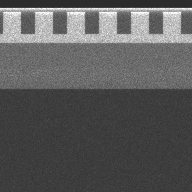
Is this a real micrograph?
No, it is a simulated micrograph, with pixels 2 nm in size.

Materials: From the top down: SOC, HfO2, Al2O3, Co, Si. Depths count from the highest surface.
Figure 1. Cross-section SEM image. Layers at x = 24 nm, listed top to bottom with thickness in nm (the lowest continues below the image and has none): SOC 8, HfO2 62, Al2O3 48, Co 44, Si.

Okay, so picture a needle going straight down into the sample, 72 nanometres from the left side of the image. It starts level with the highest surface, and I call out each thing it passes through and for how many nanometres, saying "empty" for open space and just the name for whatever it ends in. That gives SOC 8, HfO2 62, Al2O3 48, Co 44, Si